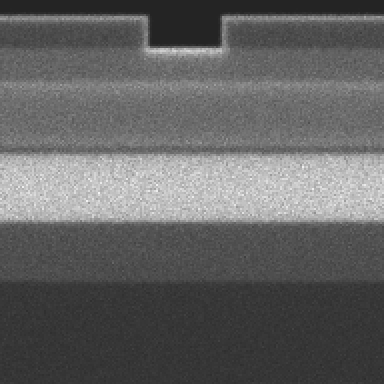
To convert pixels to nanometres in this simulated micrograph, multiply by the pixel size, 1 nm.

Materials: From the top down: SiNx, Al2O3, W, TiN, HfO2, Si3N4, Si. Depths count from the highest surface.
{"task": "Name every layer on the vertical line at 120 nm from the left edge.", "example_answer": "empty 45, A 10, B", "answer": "SiNx 32, Al2O3 34, W 64, TiN 8, HfO2 68, Si3N4 60, Si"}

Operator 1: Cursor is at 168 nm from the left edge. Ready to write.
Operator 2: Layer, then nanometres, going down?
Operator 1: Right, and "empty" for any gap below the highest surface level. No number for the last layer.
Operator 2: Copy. empty 32, Al2O3 34, W 64, TiN 8, HfO2 68, Si3N4 60, Si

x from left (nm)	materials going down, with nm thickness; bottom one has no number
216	empty 32, Al2O3 34, W 64, TiN 8, HfO2 68, Si3N4 60, Si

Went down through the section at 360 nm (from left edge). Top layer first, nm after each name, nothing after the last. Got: SiNx 32, Al2O3 34, W 64, TiN 8, HfO2 68, Si3N4 60, Si